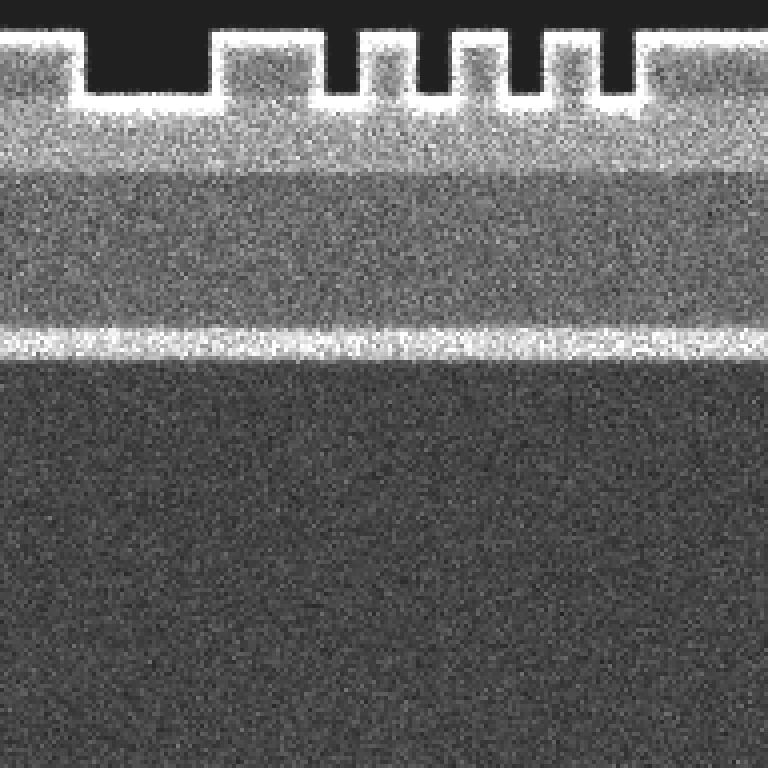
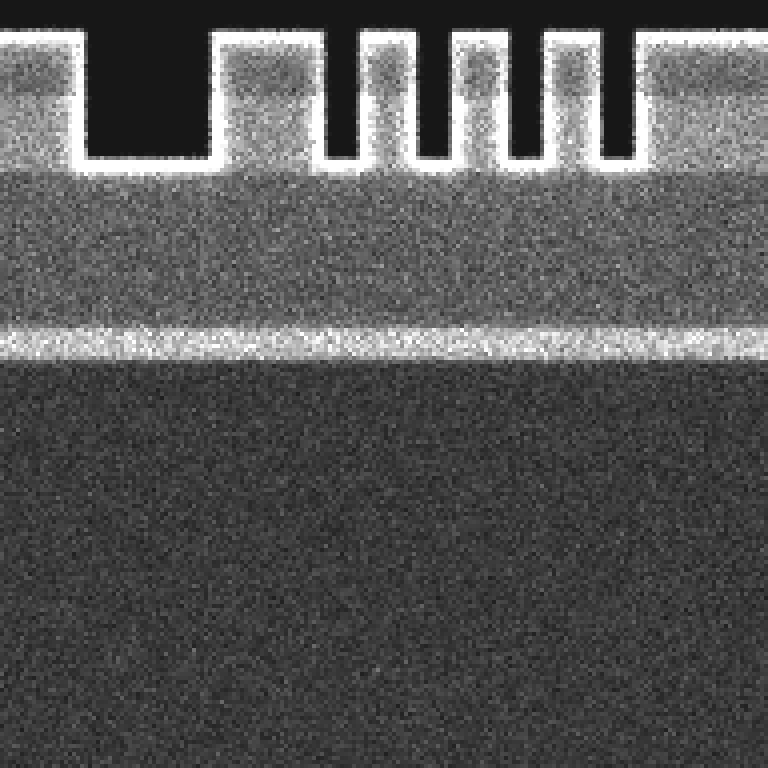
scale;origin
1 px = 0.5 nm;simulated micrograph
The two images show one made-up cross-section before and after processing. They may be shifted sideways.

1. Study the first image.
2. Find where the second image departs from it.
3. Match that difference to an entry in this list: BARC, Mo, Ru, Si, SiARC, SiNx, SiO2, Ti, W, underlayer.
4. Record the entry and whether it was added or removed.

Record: SiO2 / removed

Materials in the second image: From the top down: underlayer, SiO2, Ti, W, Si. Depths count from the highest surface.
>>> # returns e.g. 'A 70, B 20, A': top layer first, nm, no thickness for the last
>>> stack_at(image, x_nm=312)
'empty 64, SiO2 6, Ti 78, W 16, Si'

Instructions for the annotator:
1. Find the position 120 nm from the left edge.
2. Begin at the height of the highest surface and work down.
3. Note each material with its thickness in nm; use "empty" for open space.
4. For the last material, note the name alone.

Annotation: underlayer 32, SiO2 38, Ti 78, W 16, Si